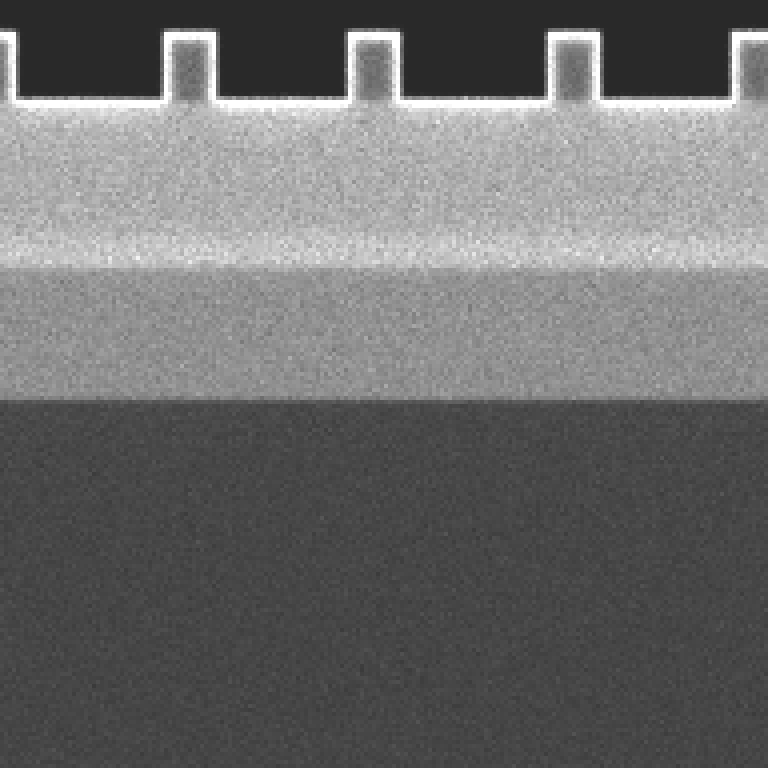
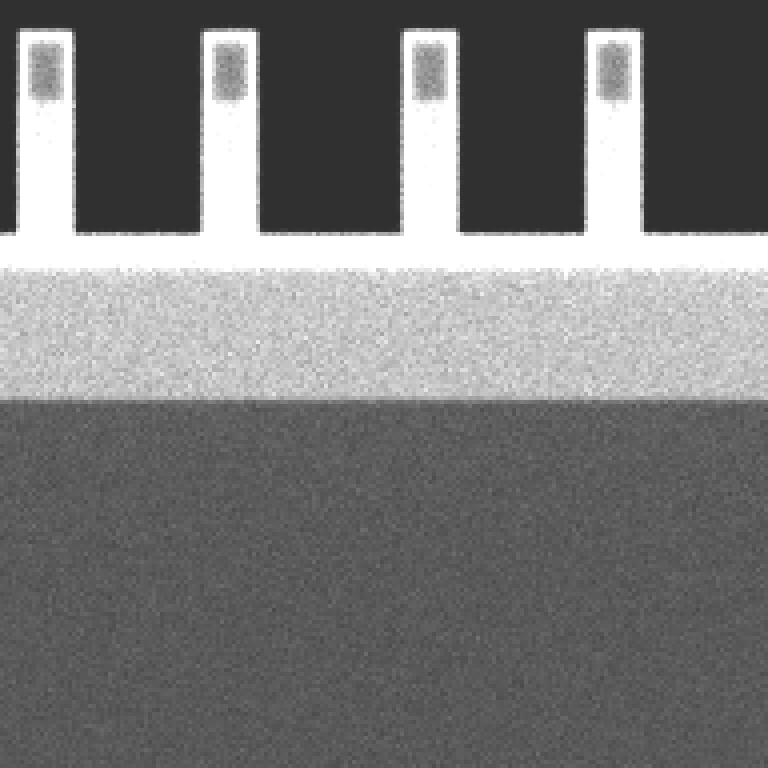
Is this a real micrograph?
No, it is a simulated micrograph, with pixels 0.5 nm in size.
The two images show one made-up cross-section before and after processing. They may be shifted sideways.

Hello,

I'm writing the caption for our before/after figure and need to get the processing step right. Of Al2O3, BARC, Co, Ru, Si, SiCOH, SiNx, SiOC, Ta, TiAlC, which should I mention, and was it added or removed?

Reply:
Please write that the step removed Co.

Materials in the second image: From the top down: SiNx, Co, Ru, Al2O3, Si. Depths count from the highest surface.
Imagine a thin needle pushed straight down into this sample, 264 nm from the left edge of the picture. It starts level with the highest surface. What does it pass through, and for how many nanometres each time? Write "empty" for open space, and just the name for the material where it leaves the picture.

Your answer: empty 102, Ru 16, Al2O3 66, Si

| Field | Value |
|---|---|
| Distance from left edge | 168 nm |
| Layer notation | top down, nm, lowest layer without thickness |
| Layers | empty 102, Ru 16, Al2O3 66, Si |